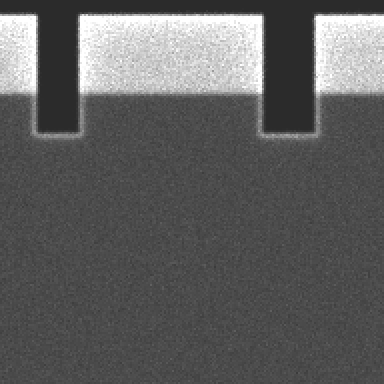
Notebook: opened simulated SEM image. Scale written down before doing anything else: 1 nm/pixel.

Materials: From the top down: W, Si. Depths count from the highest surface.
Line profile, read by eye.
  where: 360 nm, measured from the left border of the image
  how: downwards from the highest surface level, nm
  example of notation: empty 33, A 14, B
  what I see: W 78, Si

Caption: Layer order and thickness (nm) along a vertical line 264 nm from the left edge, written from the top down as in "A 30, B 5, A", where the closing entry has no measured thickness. empty 118, Si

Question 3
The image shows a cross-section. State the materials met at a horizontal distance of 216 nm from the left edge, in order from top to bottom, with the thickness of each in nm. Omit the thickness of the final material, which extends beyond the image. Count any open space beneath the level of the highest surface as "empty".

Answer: W 78, Si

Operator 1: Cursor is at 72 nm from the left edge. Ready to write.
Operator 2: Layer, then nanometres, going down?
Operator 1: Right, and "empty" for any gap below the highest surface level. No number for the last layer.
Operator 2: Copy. empty 118, Si